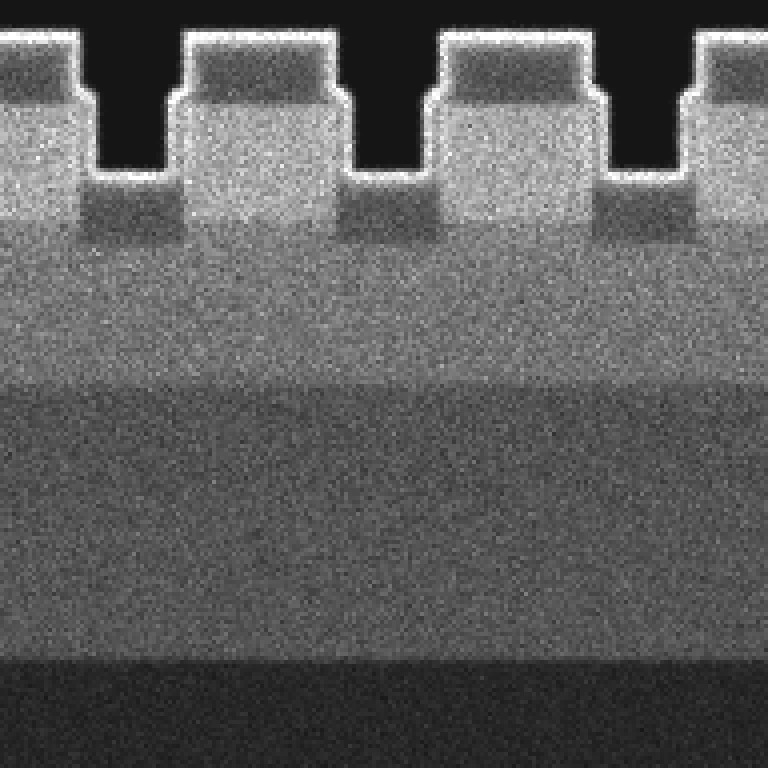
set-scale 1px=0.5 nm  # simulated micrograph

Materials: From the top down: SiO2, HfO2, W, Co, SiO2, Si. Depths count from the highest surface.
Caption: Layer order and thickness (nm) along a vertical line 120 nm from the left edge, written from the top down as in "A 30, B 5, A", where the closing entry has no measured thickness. SiO2 36, HfO2 58, W 82, Co 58, SiO2 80, Si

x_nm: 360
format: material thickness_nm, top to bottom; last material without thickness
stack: SiO2 36, HfO2 58, W 82, Co 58, SiO2 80, Si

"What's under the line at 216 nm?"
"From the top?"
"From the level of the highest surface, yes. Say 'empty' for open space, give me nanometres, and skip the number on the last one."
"empty 28, SiO2 78, W 70, Co 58, SiO2 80, Si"